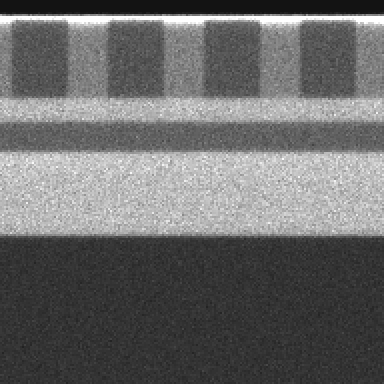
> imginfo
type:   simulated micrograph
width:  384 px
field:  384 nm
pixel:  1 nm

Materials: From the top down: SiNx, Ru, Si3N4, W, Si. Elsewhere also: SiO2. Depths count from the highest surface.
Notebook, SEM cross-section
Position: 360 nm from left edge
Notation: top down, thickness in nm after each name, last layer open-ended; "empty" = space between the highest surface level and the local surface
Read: SiO2 82, Ru 24, Si3N4 30, W 84, Si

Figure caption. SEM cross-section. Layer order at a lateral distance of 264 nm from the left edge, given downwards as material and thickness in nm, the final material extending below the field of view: SiO2 82, Ru 24, Si3N4 30, W 84, Si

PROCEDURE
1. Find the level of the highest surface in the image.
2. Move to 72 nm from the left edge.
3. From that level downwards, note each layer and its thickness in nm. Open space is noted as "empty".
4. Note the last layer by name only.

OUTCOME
SiO2 82, Ru 24, Si3N4 30, W 84, Si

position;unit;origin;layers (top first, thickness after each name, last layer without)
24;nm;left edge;SiNx 82, Ru 24, Si3N4 30, W 84, Si